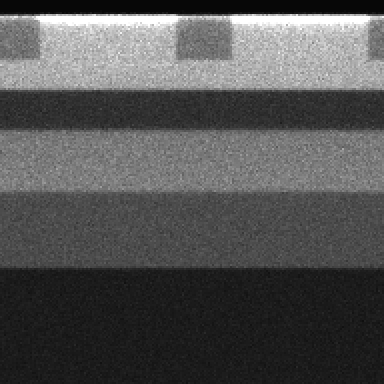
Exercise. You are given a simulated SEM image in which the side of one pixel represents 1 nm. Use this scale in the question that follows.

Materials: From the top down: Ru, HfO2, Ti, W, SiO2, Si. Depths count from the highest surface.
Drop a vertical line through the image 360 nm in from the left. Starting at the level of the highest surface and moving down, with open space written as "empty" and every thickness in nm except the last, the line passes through HfO2 74, Ti 40, W 62, SiO2 76, Si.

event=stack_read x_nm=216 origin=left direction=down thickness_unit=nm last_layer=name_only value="Ru 44, HfO2 30, Ti 40, W 62, SiO2 76, Si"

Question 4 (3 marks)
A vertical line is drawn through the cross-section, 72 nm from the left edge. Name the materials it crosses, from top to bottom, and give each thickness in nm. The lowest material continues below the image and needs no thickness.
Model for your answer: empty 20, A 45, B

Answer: HfO2 74, Ti 40, W 62, SiO2 76, Si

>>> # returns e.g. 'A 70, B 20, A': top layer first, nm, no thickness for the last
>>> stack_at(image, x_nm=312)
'HfO2 74, Ti 40, W 62, SiO2 76, Si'